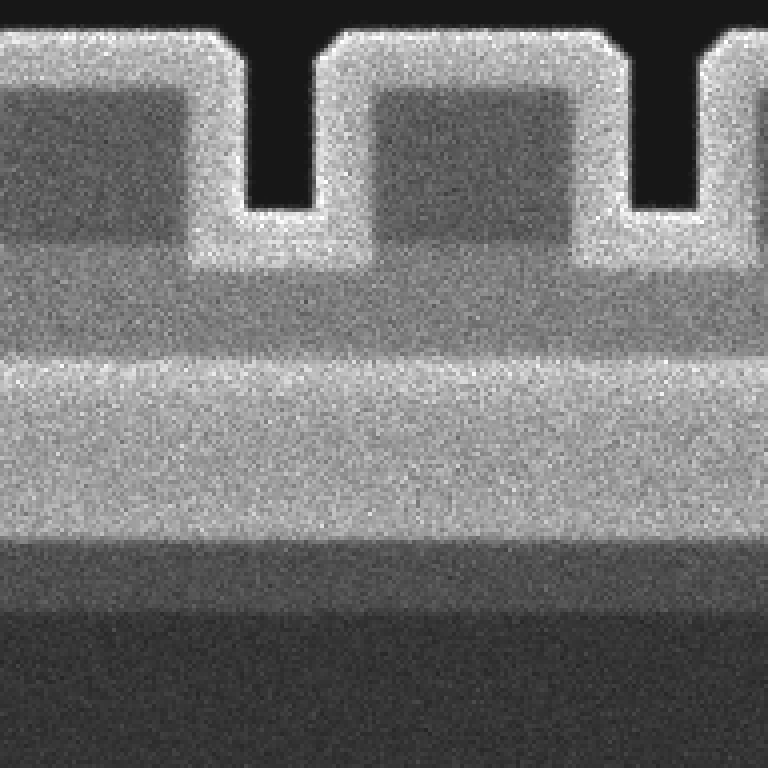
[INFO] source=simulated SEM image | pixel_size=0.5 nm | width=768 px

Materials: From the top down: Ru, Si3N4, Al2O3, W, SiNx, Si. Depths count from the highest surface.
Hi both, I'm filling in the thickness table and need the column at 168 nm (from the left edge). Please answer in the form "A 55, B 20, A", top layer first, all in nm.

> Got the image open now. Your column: empty 4, Ru 114, Al2O3 46, W 90, SiNx 36, Si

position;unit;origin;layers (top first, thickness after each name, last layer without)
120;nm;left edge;empty 14, Ru 104, Al2O3 46, W 90, SiNx 36, Si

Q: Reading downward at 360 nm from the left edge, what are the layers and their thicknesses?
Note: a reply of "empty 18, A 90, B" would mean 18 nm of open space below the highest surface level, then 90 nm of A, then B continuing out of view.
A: empty 4, Ru 114, Al2O3 46, W 90, SiNx 36, Si